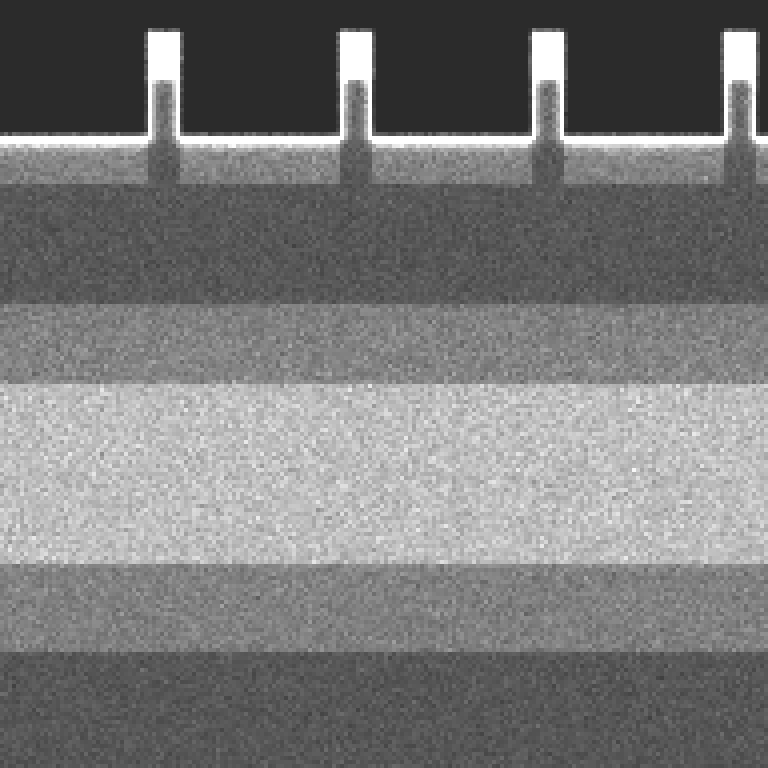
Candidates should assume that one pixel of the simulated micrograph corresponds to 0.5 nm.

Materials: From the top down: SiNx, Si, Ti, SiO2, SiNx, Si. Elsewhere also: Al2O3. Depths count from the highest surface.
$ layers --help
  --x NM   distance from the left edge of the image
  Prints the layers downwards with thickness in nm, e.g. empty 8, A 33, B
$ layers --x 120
empty 52, SiNx 24, Si 60, Ti 40, SiO2 90, SiNx 44, Si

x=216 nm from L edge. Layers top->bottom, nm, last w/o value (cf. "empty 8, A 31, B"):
empty 52, SiNx 24, Si 60, Ti 40, SiO2 90, SiNx 44, Si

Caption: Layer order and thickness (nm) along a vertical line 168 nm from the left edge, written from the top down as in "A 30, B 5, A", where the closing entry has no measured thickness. empty 52, SiNx 24, Si 60, Ti 40, SiO2 90, SiNx 44, Si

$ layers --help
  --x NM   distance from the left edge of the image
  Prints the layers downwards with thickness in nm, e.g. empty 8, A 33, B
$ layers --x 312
empty 52, SiNx 24, Si 60, Ti 40, SiO2 90, SiNx 44, Si